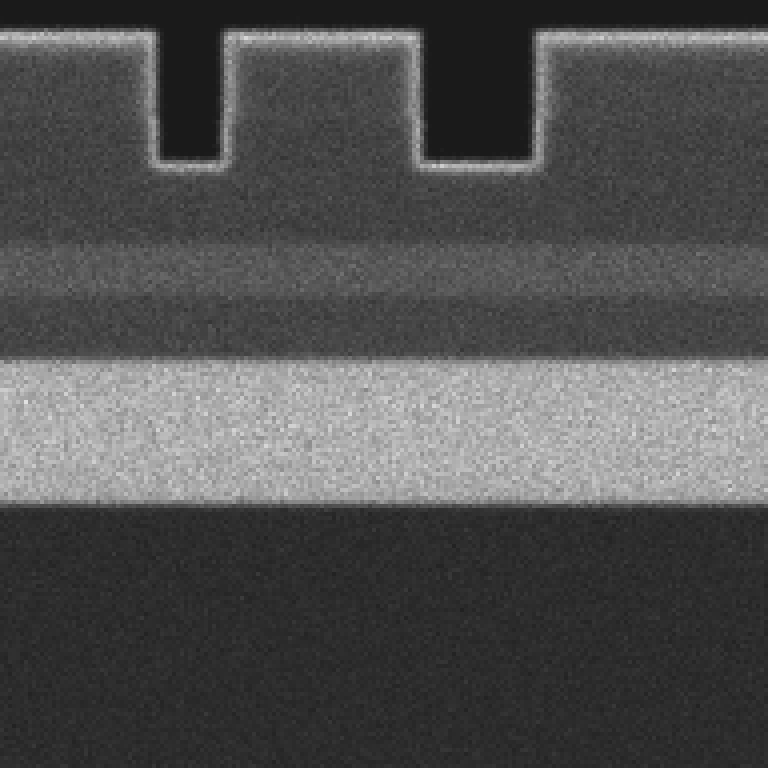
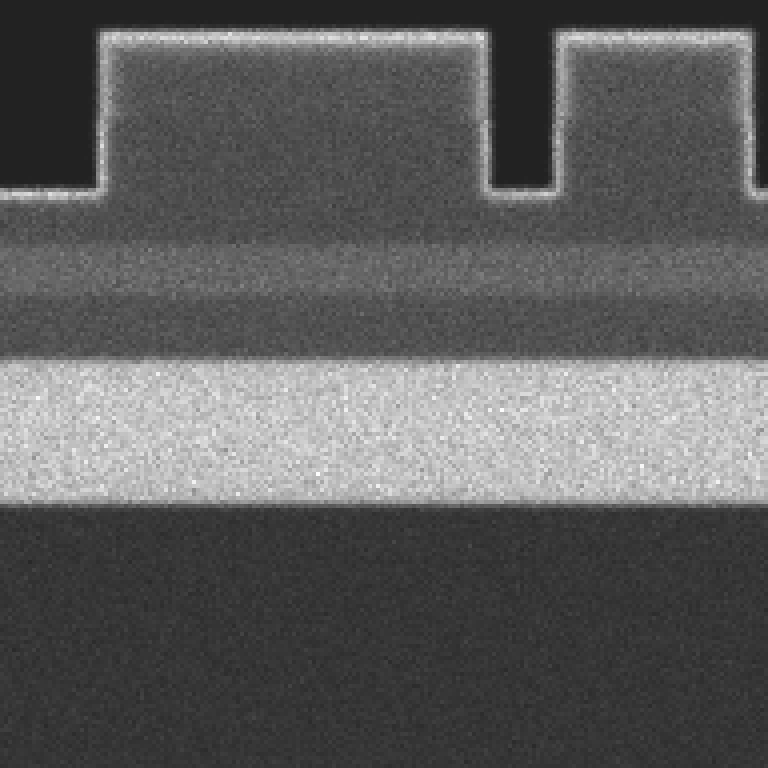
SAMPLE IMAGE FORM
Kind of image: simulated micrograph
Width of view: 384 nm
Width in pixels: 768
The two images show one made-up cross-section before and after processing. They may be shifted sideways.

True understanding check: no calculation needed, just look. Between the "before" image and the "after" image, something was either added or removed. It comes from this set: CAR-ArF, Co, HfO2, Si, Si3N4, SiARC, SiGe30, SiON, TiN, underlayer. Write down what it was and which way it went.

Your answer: TiN (removed)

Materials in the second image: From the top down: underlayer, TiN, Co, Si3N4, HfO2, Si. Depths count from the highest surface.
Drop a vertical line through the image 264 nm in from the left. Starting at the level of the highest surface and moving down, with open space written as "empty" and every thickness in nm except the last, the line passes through empty 80, TiN 26, Co 26, Si3N4 32, HfO2 72, Si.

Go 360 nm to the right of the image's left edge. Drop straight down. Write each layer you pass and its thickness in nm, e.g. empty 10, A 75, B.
underlayer 44, TiN 62, Co 26, Si3N4 32, HfO2 72, Si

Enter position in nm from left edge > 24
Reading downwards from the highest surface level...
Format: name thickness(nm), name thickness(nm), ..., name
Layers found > empty 80, TiN 26, Co 26, Si3N4 32, HfO2 72, Si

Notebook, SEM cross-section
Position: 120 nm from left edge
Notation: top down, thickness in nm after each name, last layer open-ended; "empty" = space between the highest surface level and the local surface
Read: underlayer 44, TiN 62, Co 26, Si3N4 32, HfO2 72, Si